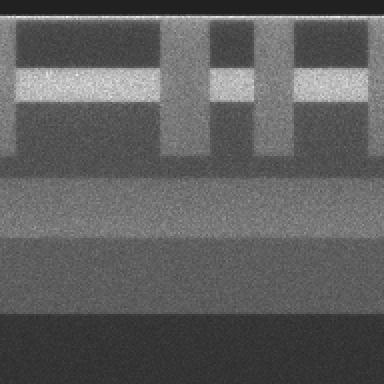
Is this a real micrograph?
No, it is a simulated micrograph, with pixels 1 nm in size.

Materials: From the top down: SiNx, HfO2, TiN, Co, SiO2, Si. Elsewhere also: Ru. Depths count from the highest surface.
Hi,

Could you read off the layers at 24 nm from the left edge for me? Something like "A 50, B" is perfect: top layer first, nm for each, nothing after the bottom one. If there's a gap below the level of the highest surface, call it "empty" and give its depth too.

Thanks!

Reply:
SiNx 52, HfO2 34, TiN 76, Co 60, SiO2 76, Si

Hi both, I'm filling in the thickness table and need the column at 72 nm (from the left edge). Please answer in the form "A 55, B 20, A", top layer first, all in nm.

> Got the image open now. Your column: SiNx 52, HfO2 34, TiN 76, Co 60, SiO2 76, Si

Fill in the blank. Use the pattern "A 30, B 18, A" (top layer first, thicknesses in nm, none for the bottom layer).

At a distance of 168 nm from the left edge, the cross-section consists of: Ru 140, TiN 22, Co 60, SiO2 76, Si